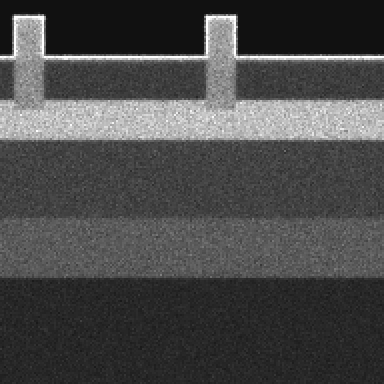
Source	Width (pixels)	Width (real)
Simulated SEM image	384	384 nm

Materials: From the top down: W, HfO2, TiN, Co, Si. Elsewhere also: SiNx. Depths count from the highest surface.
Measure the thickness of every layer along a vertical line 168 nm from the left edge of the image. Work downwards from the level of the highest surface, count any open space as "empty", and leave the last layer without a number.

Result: empty 40, SiNx 44, HfO2 40, TiN 78, Co 60, Si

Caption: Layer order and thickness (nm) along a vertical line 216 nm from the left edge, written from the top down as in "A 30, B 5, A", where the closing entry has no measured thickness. W 94, HfO2 30, TiN 78, Co 60, Si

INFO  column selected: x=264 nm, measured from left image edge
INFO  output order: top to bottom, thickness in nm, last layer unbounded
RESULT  empty 40, SiNx 44, HfO2 40, TiN 78, Co 60, Si